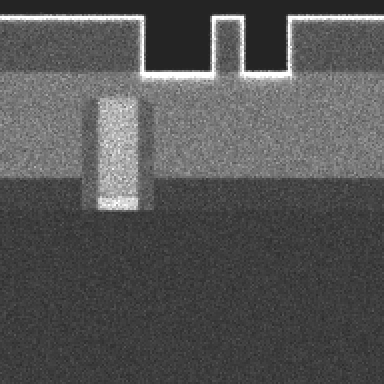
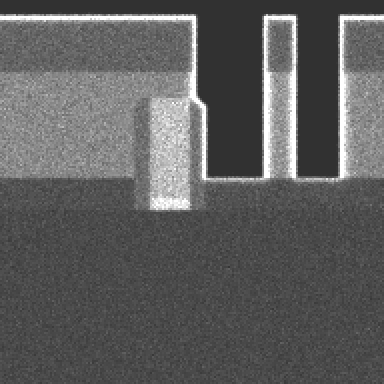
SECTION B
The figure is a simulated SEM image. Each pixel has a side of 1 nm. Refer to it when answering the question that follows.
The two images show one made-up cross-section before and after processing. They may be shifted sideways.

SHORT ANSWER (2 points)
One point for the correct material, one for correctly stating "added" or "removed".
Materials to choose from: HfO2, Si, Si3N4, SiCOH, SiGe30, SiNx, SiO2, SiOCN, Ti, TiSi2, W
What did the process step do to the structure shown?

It removed SiO2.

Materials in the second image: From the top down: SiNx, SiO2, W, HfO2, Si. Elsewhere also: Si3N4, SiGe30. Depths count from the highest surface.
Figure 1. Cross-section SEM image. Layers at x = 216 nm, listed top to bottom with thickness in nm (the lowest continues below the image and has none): empty 162, SiGe30 32, Si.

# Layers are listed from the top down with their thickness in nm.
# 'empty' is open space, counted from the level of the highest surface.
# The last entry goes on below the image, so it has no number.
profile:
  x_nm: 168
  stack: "SiNx 56, SiO2 26, W 100, HfO2 12, Si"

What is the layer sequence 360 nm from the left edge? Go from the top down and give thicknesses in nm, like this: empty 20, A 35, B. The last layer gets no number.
SiNx 56, SiO2 106, SiGe30 32, Si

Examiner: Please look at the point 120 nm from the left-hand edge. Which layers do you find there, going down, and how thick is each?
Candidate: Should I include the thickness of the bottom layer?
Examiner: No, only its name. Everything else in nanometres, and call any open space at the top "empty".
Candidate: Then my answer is SiNx 56, SiO2 106, SiGe30 32, Si